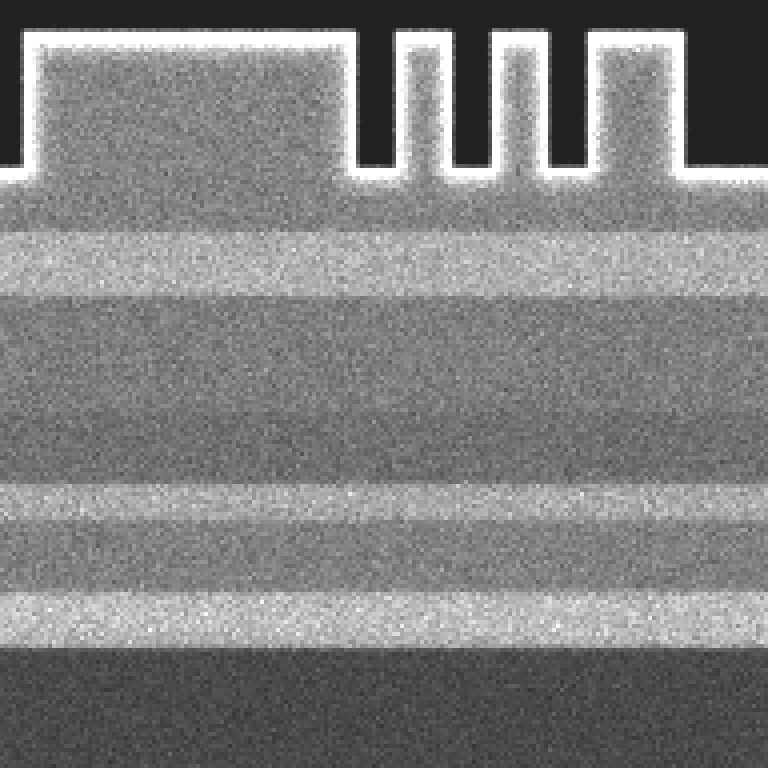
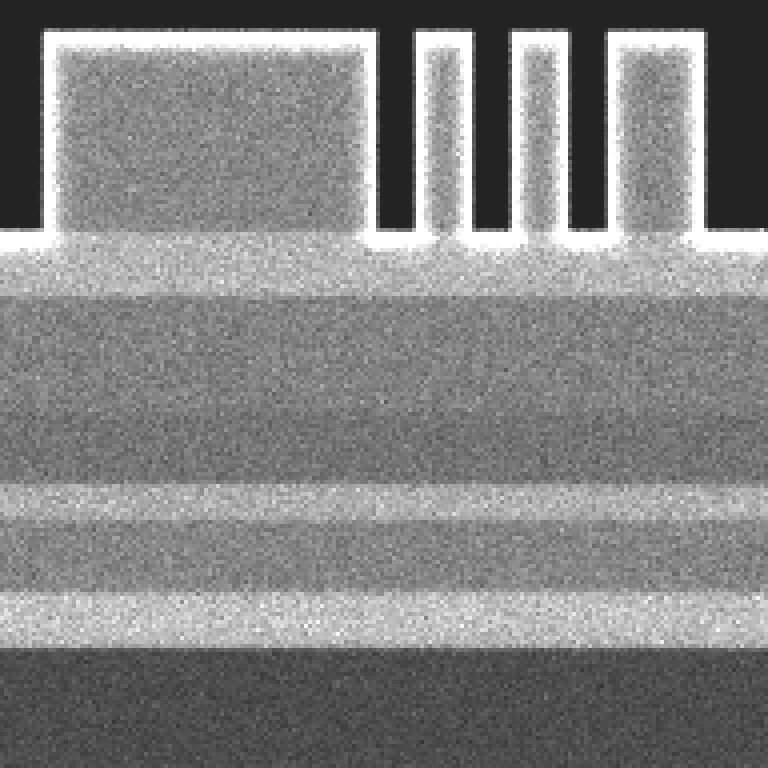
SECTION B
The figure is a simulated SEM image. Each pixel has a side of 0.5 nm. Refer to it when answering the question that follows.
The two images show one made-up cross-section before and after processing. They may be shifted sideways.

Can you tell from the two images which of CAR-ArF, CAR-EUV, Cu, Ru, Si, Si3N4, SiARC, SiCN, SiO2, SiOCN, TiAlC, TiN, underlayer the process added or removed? Yes, it removed underlayer.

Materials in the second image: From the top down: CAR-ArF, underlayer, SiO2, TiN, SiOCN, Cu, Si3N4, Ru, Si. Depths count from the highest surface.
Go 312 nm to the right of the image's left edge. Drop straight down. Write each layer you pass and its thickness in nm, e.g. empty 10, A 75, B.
CAR-ArF 68, underlayer 32, SiO2 32, TiN 58, SiOCN 36, Cu 18, Si3N4 36, Ru 28, Si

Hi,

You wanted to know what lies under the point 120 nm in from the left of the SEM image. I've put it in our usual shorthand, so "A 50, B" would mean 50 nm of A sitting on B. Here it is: CAR-ArF 68, underlayer 32, SiO2 32, TiN 58, SiOCN 36, Cu 18, Si3N4 36, Ru 28, Si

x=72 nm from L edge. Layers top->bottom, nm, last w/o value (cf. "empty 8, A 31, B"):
CAR-ArF 68, underlayer 32, SiO2 32, TiN 58, SiOCN 36, Cu 18, Si3N4 36, Ru 28, Si